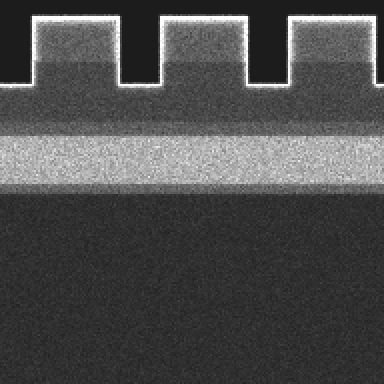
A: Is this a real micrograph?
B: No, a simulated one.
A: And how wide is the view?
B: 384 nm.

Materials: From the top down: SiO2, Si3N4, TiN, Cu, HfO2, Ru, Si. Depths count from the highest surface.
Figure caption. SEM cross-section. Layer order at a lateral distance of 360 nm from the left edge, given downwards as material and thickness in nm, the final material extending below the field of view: SiO2 46, Si3N4 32, TiN 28, Cu 14, HfO2 48, Ru 10, Si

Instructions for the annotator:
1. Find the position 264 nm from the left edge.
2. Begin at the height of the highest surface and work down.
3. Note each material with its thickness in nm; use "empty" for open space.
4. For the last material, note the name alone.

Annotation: empty 68, Si3N4 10, TiN 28, Cu 14, HfO2 48, Ru 10, Si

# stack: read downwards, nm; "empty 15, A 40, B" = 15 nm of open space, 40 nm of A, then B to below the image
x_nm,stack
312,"SiO2 46, Si3N4 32, TiN 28, Cu 14, HfO2 48, Ru 10, Si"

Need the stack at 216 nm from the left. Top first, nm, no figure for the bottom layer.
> SiO2 46, Si3N4 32, TiN 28, Cu 14, HfO2 48, Ru 10, Si